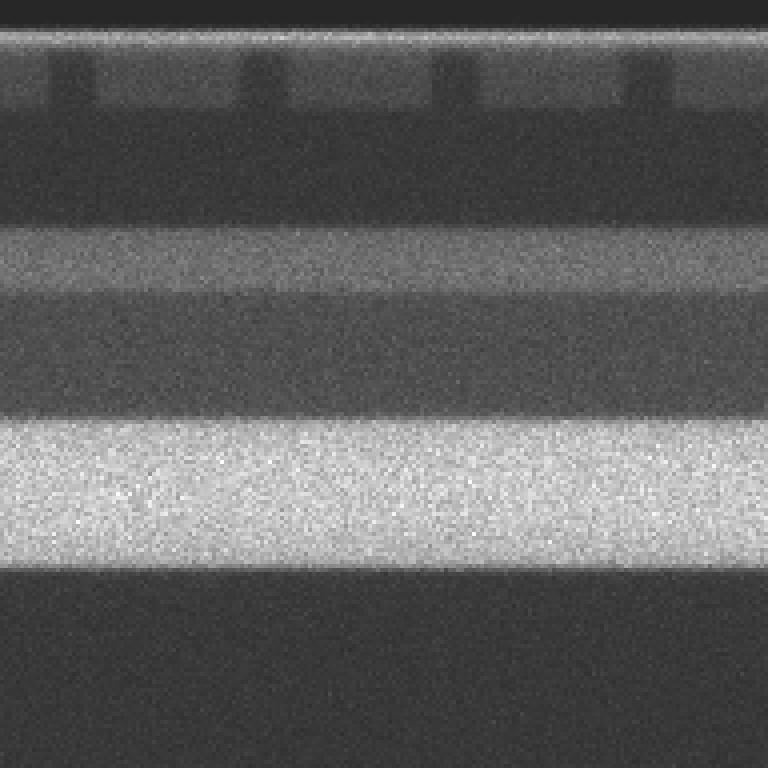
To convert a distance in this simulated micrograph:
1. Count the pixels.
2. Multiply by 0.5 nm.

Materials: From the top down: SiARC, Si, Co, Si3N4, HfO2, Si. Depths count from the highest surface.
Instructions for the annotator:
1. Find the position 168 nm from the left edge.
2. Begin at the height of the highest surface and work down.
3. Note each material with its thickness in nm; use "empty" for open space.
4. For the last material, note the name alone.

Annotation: SiARC 38, Si 60, Co 32, Si3N4 64, HfO2 74, Si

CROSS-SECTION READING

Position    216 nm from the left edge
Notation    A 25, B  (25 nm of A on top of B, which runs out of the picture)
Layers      SiARC 8, Si 90, Co 32, Si3N4 64, HfO2 74, Si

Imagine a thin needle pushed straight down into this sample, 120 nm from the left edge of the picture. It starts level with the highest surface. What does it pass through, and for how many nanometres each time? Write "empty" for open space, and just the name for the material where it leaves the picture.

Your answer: SiARC 8, Si 90, Co 32, Si3N4 64, HfO2 74, Si